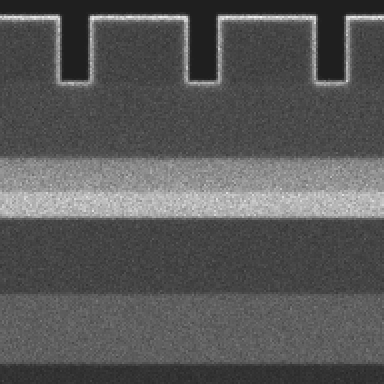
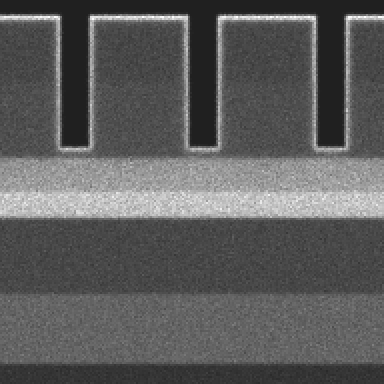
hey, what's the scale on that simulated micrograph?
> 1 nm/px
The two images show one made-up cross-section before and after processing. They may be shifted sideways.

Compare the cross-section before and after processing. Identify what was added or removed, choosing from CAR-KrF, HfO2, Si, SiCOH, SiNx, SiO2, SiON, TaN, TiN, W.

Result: TiN removed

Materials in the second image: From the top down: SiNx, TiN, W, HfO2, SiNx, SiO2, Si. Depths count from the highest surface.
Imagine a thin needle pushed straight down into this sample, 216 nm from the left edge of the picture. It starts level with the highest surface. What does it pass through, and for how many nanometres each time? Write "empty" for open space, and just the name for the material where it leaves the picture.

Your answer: empty 132, TiN 10, W 34, HfO2 26, SiNx 76, SiO2 70, Si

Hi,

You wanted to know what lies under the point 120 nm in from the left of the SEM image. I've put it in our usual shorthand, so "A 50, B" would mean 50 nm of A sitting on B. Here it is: SiNx 66, TiN 76, W 34, HfO2 26, SiNx 76, SiO2 70, Si